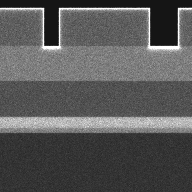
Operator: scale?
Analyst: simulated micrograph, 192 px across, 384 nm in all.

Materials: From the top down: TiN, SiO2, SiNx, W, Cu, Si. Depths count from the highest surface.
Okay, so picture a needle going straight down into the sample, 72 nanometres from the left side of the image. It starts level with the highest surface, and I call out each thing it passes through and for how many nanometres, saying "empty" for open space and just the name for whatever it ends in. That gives TiN 76, SiO2 70, SiNx 72, W 22, Cu 10, Si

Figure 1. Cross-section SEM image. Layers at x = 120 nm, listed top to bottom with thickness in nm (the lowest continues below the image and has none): TiN 76, SiO2 70, SiNx 72, W 22, Cu 10, Si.